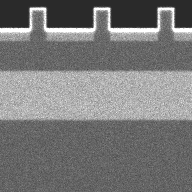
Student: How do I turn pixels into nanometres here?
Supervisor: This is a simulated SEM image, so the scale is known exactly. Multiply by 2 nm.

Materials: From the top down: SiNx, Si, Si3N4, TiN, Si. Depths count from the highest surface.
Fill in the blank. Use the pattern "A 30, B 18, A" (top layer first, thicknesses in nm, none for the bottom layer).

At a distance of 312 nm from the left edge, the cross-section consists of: empty 42, SiNx 24, Si 60, Si3N4 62, TiN 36, Si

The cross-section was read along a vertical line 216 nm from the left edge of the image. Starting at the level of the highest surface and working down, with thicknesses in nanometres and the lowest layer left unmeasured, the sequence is Si 126, Si3N4 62, TiN 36, Si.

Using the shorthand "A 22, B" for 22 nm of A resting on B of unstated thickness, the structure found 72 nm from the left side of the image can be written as Si 126, Si3N4 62, TiN 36, Si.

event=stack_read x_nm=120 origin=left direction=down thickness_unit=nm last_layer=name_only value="empty 42, SiNx 24, Si 60, Si3N4 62, TiN 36, Si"